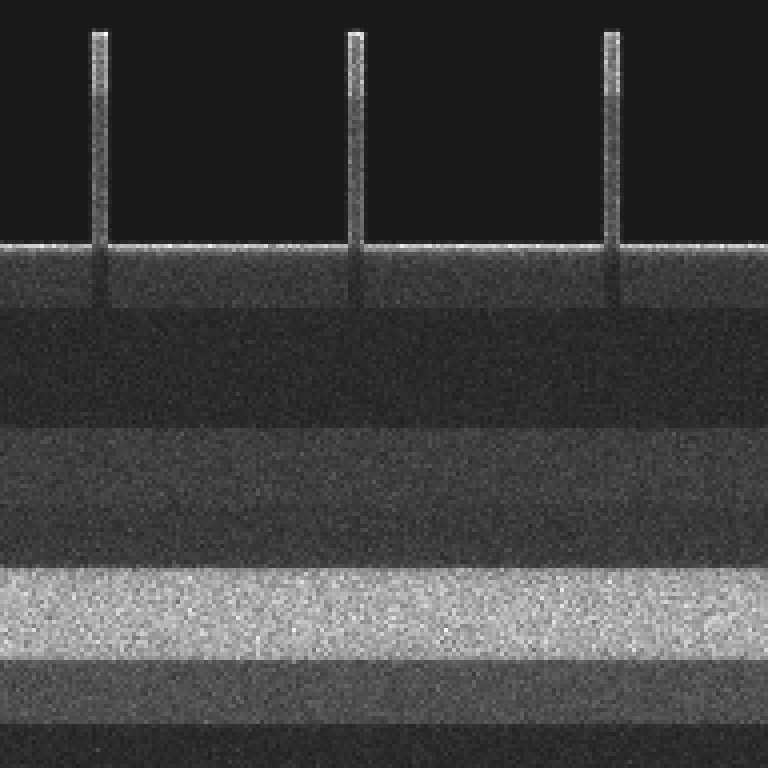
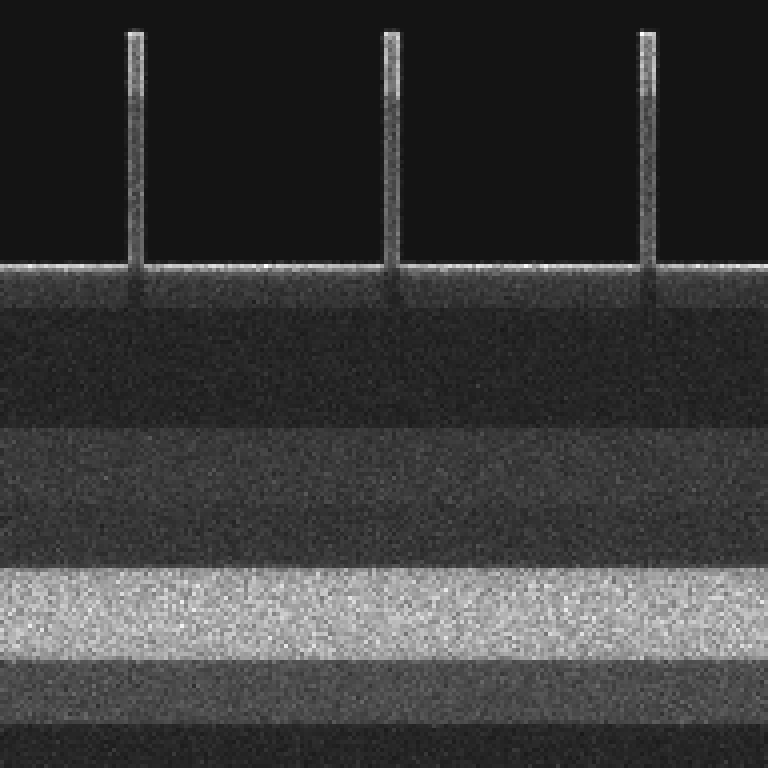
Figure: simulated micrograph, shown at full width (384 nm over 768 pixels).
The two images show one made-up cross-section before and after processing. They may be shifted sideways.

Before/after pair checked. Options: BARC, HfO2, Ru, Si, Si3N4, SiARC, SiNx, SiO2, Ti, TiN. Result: removed SiNx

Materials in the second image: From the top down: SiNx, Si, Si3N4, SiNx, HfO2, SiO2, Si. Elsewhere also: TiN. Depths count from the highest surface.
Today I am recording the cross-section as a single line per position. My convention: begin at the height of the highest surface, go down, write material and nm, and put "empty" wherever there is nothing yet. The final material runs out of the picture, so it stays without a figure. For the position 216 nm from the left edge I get empty 116, SiNx 22, Si 60, Si3N4 38, SiNx 32, HfO2 46, SiO2 32, Si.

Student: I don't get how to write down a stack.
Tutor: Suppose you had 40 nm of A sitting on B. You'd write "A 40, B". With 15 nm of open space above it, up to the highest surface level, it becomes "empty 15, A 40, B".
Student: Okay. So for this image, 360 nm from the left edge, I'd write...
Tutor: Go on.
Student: empty 116, SiNx 22, Si 60, Si3N4 38, SiNx 32, HfO2 46, SiO2 32, Si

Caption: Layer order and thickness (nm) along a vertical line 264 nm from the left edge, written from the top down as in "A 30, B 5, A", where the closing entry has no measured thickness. empty 116, SiNx 22, Si 60, Si3N4 38, SiNx 32, HfO2 46, SiO2 32, Si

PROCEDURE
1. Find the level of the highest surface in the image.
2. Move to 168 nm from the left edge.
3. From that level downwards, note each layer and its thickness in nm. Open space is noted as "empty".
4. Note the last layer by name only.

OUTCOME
empty 116, SiNx 22, Si 60, Si3N4 38, SiNx 32, HfO2 46, SiO2 32, Si